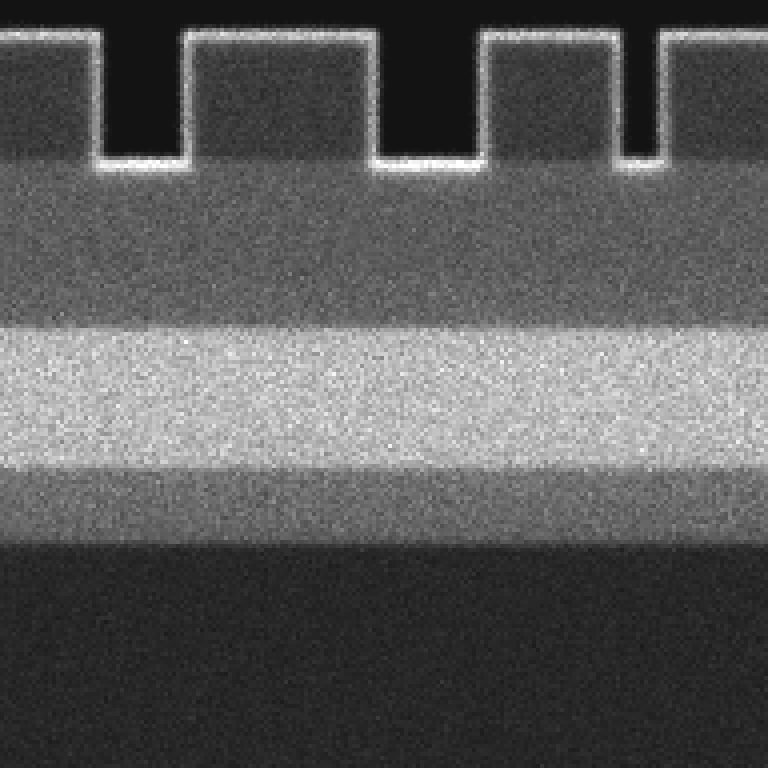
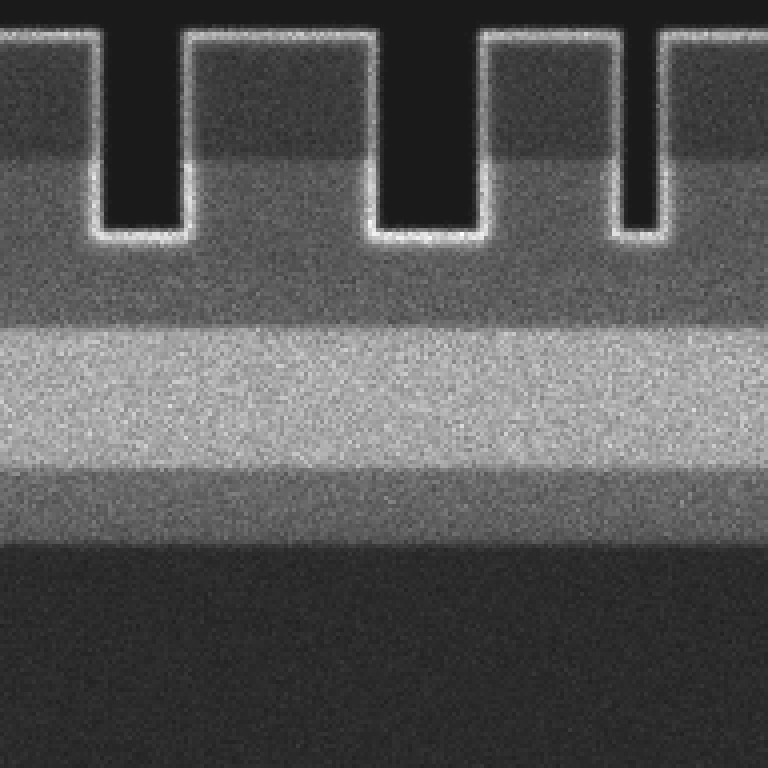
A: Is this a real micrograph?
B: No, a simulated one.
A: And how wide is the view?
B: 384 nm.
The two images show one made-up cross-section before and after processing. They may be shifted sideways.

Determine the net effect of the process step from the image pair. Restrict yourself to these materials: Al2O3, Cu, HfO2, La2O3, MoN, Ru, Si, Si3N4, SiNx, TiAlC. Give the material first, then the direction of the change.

Al2O3: removed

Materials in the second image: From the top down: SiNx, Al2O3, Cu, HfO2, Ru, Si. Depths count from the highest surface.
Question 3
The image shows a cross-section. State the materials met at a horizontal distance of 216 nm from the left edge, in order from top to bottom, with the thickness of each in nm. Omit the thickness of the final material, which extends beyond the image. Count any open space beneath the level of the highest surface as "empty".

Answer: empty 100, Al2O3 20, Cu 28, HfO2 70, Ru 38, Si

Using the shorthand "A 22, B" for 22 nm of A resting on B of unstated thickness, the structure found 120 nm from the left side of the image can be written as SiNx 64, Al2O3 56, Cu 28, HfO2 70, Ru 38, Si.